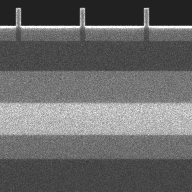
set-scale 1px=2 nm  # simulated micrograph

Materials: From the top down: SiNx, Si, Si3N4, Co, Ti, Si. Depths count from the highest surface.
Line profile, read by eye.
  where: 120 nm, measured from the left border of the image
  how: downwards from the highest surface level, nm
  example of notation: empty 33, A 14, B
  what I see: empty 36, SiNx 30, Si 60, Si3N4 64, Co 64, Ti 48, Si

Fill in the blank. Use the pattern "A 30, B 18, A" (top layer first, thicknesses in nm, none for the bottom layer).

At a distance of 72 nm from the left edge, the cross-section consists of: empty 36, SiNx 30, Si 60, Si3N4 64, Co 64, Ti 48, Si